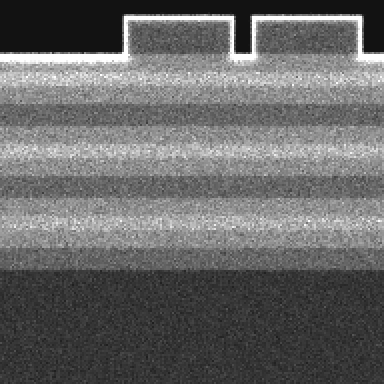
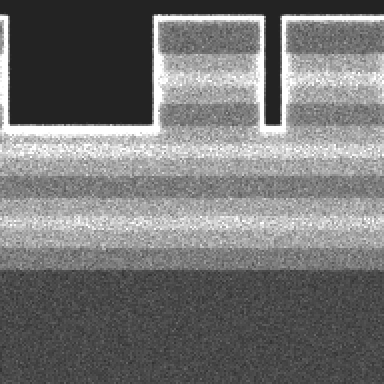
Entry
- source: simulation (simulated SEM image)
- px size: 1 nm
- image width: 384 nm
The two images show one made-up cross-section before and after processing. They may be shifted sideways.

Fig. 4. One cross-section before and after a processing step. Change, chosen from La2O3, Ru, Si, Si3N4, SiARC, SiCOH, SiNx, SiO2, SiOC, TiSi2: Ru and Si3N4 and SiO2 removed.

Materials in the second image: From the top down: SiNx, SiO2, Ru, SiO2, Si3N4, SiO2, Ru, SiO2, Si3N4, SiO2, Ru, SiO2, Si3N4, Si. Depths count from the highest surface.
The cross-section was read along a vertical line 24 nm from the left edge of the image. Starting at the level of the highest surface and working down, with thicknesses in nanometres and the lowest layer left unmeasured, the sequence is empty 110, SiO2 18, Ru 14, SiO2 18, Si3N4 22, SiO2 18, Ru 14, SiO2 18, Si3N4 22, Si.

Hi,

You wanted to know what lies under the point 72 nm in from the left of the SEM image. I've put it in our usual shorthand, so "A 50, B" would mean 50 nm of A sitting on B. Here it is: empty 110, SiO2 18, Ru 14, SiO2 18, Si3N4 22, SiO2 18, Ru 14, SiO2 18, Si3N4 22, Si